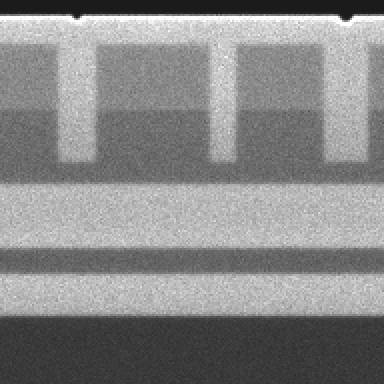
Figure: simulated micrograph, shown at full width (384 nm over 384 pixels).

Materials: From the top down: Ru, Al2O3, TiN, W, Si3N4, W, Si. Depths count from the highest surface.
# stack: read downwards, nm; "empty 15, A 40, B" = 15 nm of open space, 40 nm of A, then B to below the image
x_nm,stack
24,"Ru 28, Al2O3 66, TiN 74, W 64, Si3N4 26, W 42, Si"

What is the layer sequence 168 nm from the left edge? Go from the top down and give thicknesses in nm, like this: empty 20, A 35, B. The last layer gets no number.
Ru 28, Al2O3 66, TiN 74, W 64, Si3N4 26, W 42, Si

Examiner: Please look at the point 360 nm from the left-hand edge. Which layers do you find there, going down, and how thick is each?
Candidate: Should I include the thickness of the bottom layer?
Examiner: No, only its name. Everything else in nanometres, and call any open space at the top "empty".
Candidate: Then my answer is Ru 146, TiN 22, W 64, Si3N4 26, W 42, Si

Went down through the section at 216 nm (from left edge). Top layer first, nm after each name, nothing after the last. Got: Ru 146, TiN 22, W 64, Si3N4 26, W 42, Si